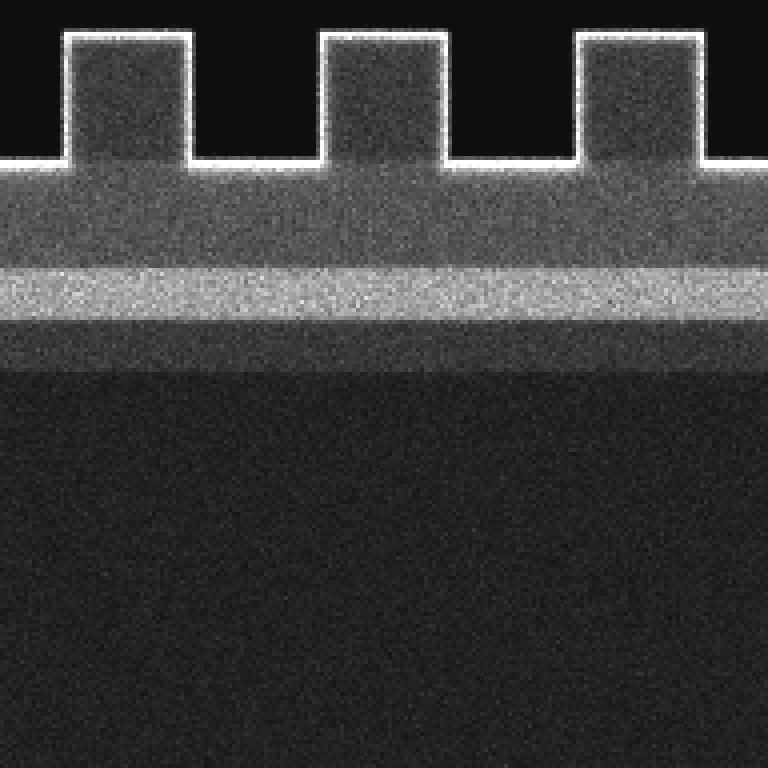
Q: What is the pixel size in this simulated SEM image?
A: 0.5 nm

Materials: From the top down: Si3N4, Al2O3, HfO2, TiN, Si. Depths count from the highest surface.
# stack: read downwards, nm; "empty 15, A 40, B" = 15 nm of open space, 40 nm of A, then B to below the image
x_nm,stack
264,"empty 64, Al2O3 54, HfO2 26, TiN 26, Si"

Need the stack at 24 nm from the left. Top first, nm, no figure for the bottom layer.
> empty 64, Al2O3 54, HfO2 26, TiN 26, Si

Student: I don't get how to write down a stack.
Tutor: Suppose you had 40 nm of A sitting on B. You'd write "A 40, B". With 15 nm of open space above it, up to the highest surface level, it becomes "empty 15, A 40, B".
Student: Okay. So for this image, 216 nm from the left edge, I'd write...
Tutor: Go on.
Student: Si3N4 64, Al2O3 54, HfO2 26, TiN 26, Si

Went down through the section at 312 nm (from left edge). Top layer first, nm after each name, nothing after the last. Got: Si3N4 64, Al2O3 54, HfO2 26, TiN 26, Si